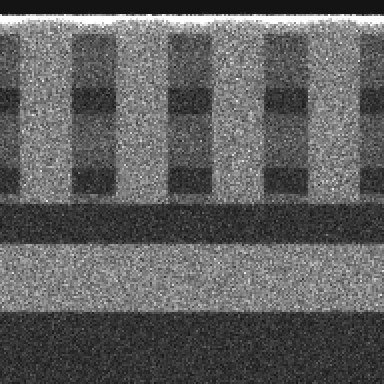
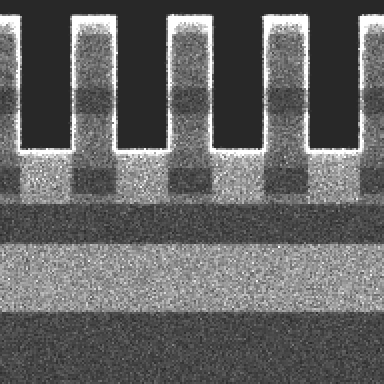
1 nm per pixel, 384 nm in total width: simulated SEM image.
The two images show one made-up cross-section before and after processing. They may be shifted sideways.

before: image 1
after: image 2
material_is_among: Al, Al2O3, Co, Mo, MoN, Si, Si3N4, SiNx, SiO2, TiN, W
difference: Co, removed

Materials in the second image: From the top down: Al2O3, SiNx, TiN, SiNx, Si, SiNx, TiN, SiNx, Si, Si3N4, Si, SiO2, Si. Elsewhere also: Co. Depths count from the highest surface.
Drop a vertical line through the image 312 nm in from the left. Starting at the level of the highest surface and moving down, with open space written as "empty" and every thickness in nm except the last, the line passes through empty 134, Co 54, Si 40, SiO2 68, Si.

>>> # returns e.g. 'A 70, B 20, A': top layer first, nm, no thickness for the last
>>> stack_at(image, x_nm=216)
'empty 134, Co 54, Si 40, SiO2 68, Si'